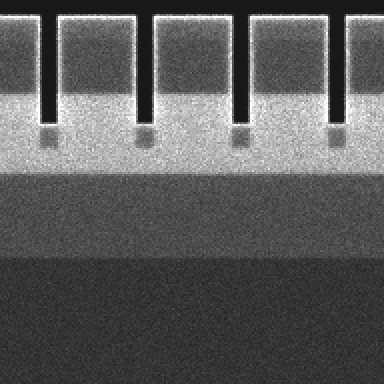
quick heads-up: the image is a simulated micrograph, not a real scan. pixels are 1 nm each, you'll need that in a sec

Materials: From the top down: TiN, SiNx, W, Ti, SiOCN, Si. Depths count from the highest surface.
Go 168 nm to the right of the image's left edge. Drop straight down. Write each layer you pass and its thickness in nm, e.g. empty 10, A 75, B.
TiN 24, SiNx 54, W 80, Ti 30, SiOCN 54, Si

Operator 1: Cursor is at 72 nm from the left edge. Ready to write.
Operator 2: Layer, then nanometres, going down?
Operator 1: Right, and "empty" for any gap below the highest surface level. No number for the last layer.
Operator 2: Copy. TiN 24, SiNx 54, W 80, Ti 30, SiOCN 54, Si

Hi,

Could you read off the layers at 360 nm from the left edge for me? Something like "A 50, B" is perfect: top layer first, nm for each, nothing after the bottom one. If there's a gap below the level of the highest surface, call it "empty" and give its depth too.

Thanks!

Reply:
TiN 24, SiNx 54, W 80, Ti 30, SiOCN 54, Si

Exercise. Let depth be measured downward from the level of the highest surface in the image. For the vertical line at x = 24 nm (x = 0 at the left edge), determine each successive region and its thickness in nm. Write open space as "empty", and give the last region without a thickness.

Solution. TiN 24, SiNx 54, W 80, Ti 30, SiOCN 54, Si